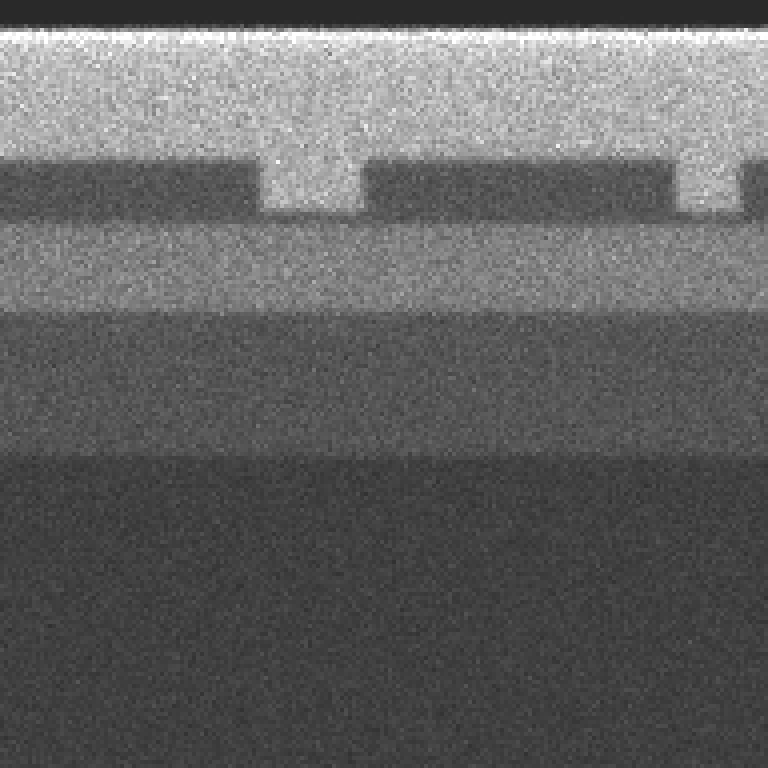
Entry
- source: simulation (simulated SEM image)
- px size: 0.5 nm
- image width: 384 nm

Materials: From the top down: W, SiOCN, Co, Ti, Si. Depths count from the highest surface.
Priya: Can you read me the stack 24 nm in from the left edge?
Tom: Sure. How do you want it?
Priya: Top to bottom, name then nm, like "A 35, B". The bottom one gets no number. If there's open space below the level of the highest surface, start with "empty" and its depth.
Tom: W 64, SiOCN 32, Co 44, Ti 72, Si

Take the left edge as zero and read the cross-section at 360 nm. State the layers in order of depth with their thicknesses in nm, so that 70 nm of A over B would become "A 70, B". W 90, SiOCN 6, Co 44, Ti 72, Si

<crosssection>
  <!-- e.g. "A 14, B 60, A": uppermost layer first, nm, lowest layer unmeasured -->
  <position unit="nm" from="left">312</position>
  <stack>W 64, SiOCN 32, Co 44, Ti 72, Si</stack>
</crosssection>